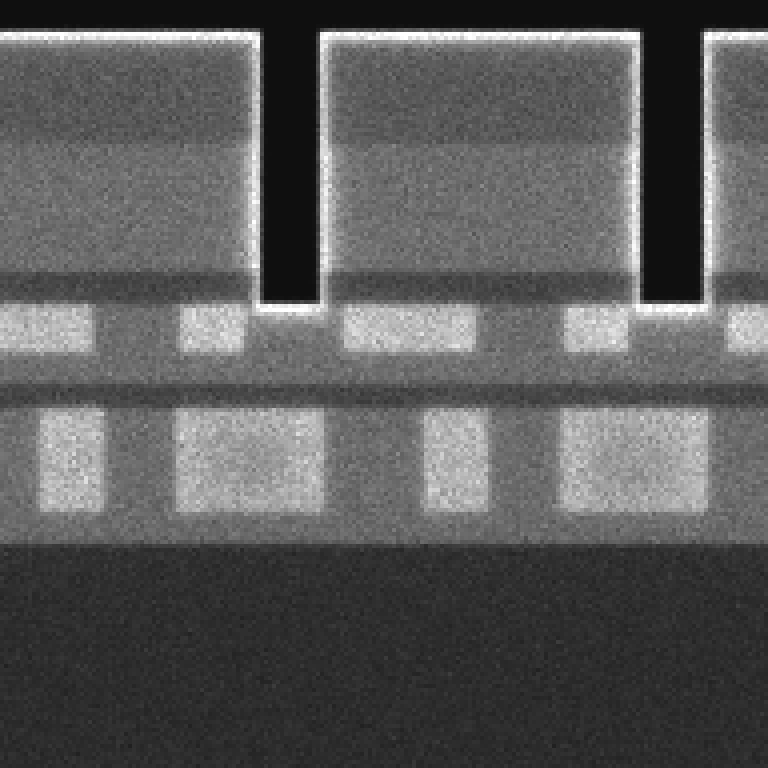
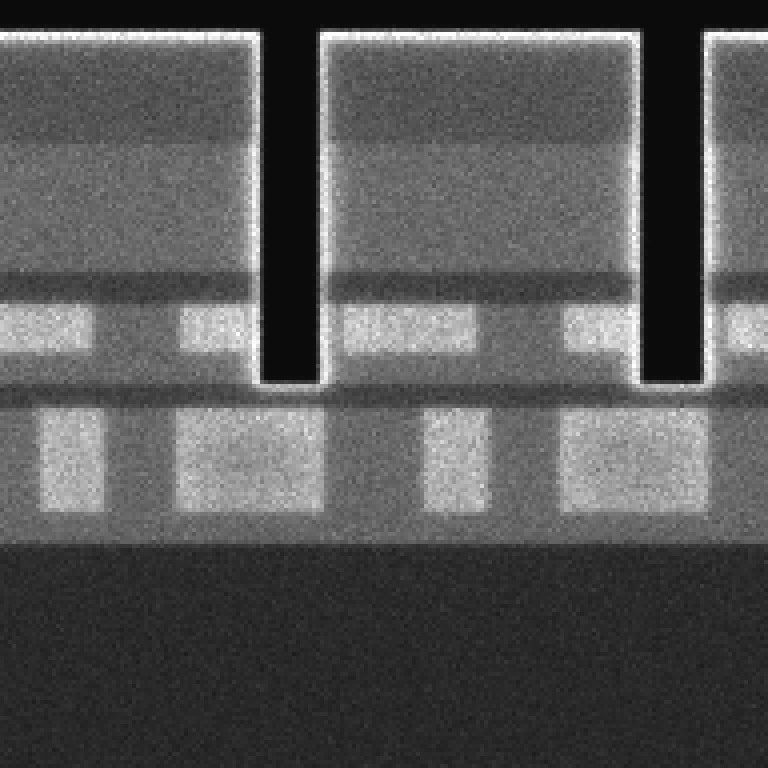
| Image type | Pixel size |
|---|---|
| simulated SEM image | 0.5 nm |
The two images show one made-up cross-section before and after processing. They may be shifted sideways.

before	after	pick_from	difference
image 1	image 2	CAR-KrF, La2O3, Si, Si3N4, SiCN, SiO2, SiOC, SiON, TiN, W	SiO2 removed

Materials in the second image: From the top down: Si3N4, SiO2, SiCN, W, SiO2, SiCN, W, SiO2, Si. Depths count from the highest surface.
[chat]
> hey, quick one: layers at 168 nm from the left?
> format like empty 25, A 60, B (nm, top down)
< Si3N4 56, SiO2 64, SiCN 16, SiO2 40, SiCN 12, SiO2 68, Si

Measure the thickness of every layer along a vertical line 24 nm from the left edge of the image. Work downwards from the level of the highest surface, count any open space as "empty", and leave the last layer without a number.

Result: Si3N4 56, SiO2 64, SiCN 16, W 24, SiO2 16, SiCN 12, W 52, SiO2 16, Si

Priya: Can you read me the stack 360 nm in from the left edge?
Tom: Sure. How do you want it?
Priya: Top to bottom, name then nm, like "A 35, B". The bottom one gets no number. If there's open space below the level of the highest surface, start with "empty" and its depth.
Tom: Si3N4 56, SiO2 64, SiCN 16, SiO2 40, SiCN 12, SiO2 68, Si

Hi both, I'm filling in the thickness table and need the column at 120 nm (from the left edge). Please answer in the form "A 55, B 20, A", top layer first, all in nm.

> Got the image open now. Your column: Si3N4 56, SiO2 64, SiCN 16, W 24, SiO2 16, SiCN 12, W 52, SiO2 16, Si